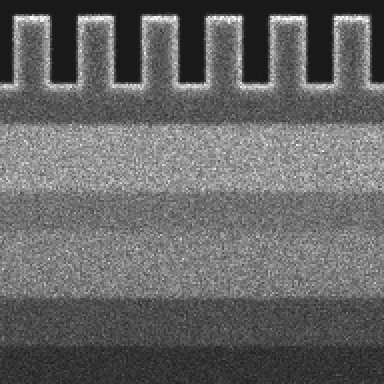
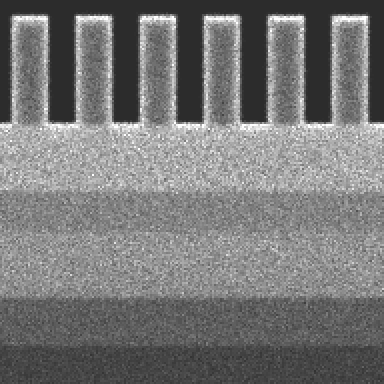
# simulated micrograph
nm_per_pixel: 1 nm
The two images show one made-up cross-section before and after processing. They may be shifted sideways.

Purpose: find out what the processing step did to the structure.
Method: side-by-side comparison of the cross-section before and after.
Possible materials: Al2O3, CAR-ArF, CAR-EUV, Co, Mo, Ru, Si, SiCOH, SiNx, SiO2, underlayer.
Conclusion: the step removed underlayer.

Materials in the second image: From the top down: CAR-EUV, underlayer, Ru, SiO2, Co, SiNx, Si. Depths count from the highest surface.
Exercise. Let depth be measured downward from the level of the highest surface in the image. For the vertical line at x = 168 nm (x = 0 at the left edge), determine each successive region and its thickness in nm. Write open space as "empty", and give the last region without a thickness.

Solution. CAR-EUV 68, underlayer 40, Ru 68, SiO2 40, Co 66, SiNx 48, Si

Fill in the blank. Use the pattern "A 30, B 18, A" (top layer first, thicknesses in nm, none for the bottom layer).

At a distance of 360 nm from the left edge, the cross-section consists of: CAR-EUV 68, underlayer 40, Ru 68, SiO2 40, Co 66, SiNx 48, Si